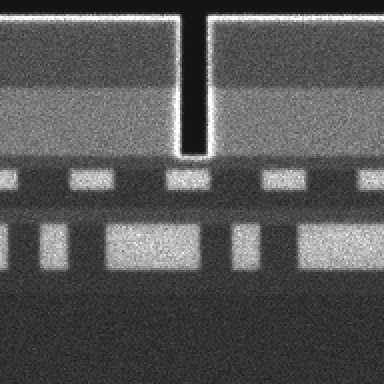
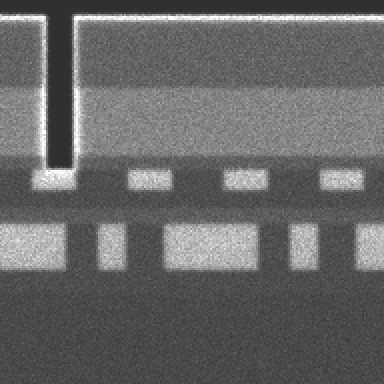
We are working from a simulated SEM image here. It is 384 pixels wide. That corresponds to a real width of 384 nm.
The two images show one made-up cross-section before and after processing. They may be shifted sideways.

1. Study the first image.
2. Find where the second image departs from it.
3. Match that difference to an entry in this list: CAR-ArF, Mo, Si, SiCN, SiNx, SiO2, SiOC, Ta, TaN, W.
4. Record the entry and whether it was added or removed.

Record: SiCN / removed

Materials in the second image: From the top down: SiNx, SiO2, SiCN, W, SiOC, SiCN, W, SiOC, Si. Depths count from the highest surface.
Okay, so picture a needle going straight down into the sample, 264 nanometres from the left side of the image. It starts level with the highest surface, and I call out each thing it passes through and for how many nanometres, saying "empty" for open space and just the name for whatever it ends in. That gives SiNx 72, SiO2 68, SiCN 14, W 20, SiOC 18, SiCN 16, SiOC 70, Si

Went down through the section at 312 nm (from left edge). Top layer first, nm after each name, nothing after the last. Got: SiNx 72, SiO2 68, SiCN 14, SiOC 38, SiCN 16, W 46, SiOC 24, Si